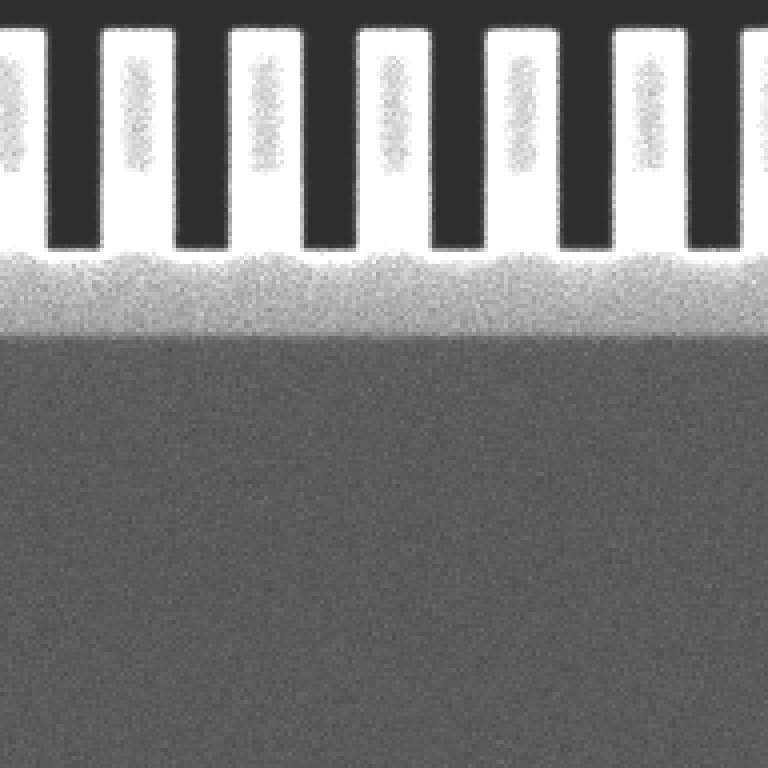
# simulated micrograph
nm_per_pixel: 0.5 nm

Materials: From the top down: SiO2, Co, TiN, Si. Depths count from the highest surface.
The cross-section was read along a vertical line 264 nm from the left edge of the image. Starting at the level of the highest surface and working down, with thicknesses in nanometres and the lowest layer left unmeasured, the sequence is SiO2 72, Co 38, TiN 42, Si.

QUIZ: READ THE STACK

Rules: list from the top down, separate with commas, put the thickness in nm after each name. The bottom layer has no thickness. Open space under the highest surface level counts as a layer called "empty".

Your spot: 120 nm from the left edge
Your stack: SiO2 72, Co 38, TiN 42, Si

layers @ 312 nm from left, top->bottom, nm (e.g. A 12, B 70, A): SiO2 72, Co 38, TiN 42, Si